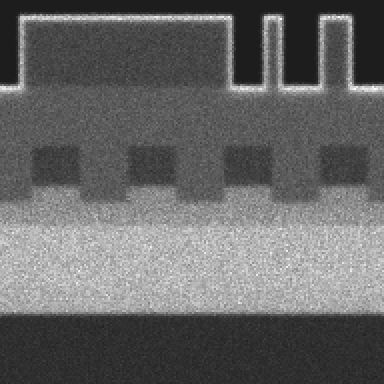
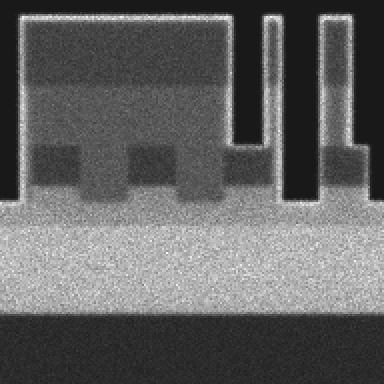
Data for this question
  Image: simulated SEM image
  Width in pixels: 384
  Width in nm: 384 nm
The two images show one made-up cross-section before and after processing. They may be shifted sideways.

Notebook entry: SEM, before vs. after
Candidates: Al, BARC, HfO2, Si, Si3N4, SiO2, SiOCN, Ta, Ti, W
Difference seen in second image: SiO2 removed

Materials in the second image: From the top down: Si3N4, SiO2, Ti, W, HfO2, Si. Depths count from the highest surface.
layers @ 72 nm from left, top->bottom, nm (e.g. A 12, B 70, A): Si3N4 70, SiO2 60, Ti 40, W 40, HfO2 88, Si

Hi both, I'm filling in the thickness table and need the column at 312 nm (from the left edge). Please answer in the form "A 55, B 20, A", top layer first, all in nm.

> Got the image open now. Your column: empty 186, W 24, HfO2 88, Si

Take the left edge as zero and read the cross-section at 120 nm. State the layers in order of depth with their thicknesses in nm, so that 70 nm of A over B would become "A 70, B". Si3N4 70, SiO2 116, W 24, HfO2 88, Si